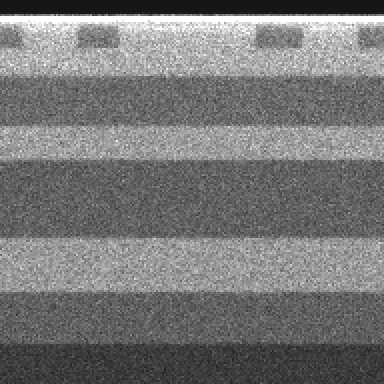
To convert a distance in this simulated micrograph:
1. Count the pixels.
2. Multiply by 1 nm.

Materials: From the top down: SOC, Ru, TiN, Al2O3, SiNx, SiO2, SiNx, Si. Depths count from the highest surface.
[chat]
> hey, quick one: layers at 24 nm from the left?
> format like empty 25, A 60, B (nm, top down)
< SOC 10, Ru 50, TiN 50, Al2O3 34, SiNx 78, SiO2 54, SiNx 52, Si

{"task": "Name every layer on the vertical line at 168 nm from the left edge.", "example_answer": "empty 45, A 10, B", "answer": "SOC 10, Ru 50, TiN 50, Al2O3 34, SiNx 78, SiO2 54, SiNx 52, Si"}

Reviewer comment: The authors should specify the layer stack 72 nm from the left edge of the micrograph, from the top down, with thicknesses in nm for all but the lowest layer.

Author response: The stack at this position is SOC 10, Ru 50, TiN 50, Al2O3 34, SiNx 78, SiO2 54, SiNx 52, Si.